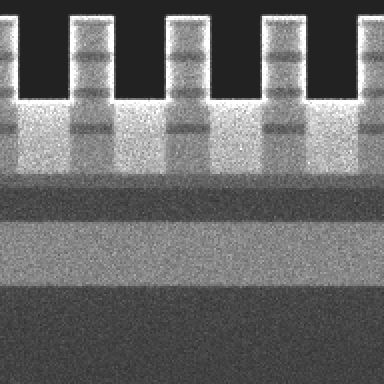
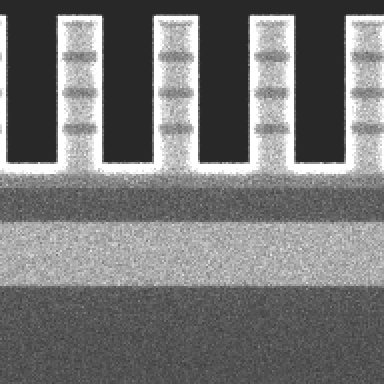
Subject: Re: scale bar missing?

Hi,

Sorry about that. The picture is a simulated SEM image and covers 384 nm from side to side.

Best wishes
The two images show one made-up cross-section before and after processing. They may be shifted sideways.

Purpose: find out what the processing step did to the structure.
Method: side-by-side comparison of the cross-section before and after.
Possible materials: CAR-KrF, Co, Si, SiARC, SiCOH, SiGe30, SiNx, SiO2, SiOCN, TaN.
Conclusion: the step removed Co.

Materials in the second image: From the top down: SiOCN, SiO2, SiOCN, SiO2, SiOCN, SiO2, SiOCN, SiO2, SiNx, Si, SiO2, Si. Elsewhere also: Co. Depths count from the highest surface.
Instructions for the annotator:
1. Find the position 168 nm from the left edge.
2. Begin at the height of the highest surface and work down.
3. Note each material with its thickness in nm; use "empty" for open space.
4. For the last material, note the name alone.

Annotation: SiOCN 10, SiO2 26, SiOCN 10, SiO2 26, SiOCN 10, SiO2 26, SiOCN 10, SiO2 40, SiNx 14, Si 34, SiO2 64, Si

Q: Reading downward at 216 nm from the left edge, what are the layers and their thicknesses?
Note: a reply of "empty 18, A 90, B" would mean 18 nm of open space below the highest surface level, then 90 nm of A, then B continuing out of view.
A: empty 148, Co 10, SiNx 14, Si 34, SiO2 64, Si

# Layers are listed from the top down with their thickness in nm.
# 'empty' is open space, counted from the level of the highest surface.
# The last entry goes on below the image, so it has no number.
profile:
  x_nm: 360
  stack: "SiOCN 10, SiO2 26, SiOCN 10, SiO2 26, SiOCN 10, SiO2 26, SiOCN 10, SiO2 40, SiNx 14, Si 34, SiO2 64, Si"